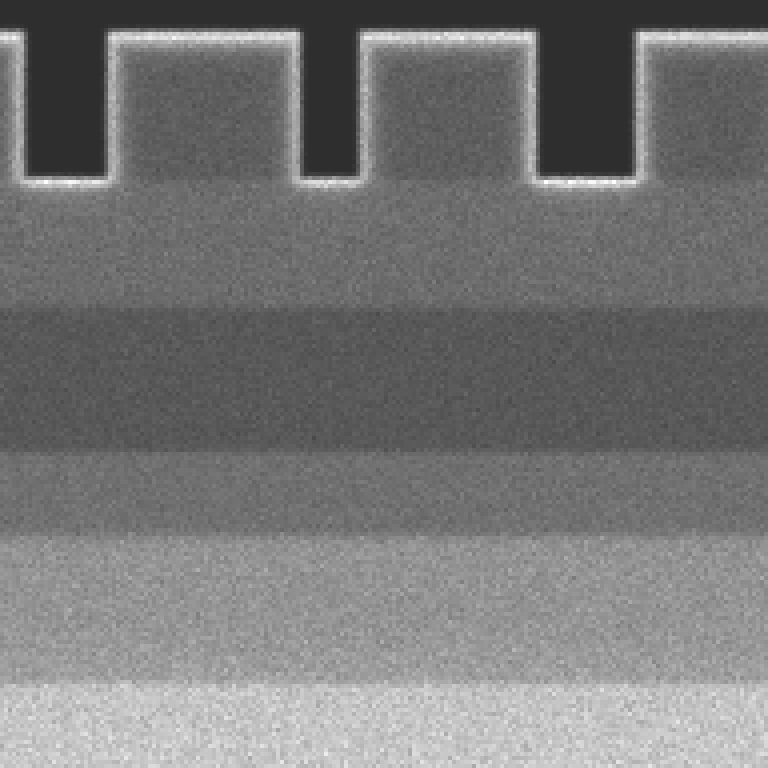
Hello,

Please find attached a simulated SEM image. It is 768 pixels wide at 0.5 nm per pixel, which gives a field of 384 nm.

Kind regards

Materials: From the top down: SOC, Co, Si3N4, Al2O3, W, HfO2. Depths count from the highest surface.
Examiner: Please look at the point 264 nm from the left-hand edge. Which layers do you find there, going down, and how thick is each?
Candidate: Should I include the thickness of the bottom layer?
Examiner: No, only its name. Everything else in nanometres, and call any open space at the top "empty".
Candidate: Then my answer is SOC 74, Co 64, Si3N4 72, Al2O3 42, W 74, HfO2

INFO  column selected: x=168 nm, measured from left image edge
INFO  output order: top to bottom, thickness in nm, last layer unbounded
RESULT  empty 74, Co 64, Si3N4 72, Al2O3 42, W 74, HfO2